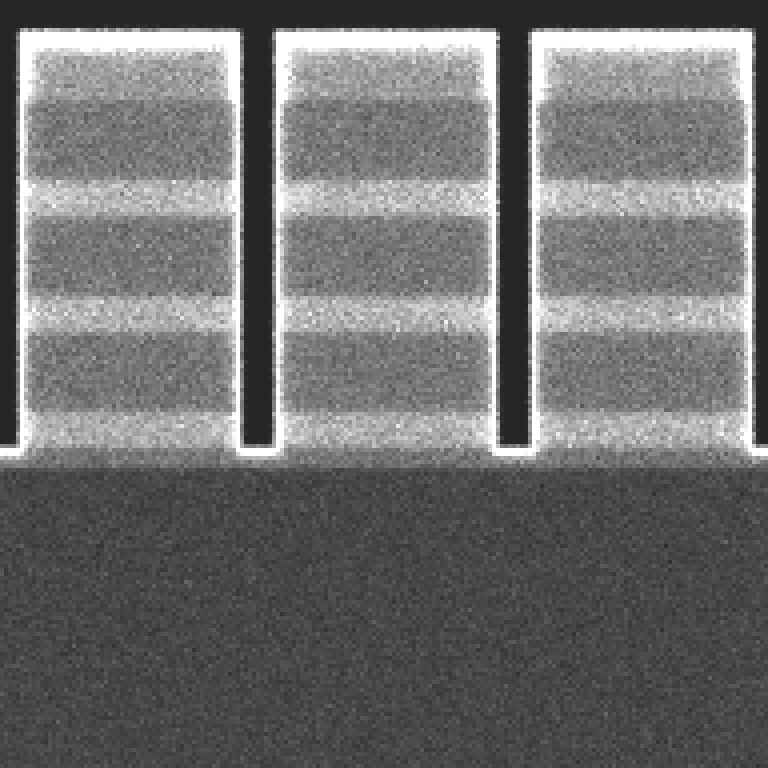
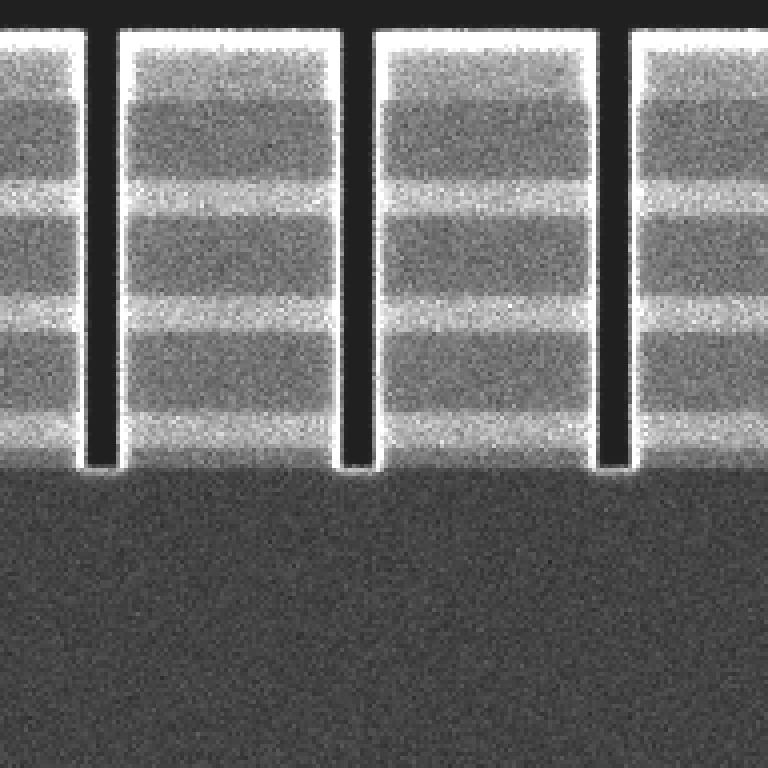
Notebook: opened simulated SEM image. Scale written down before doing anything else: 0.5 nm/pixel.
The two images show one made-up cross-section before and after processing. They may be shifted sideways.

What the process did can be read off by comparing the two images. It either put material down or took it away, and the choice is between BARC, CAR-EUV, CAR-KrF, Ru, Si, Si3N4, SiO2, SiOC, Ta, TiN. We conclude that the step removed Si3N4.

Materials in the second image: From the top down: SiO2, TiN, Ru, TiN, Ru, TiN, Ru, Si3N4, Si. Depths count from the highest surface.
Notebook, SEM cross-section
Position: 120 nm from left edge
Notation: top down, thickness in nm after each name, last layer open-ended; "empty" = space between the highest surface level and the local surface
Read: SiO2 34, TiN 40, Ru 18, TiN 40, Ru 18, TiN 40, Ru 18, Si3N4 10, Si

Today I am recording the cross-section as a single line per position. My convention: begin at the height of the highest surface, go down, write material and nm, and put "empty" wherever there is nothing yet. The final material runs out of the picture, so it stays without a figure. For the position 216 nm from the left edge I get SiO2 34, TiN 40, Ru 18, TiN 40, Ru 18, TiN 40, Ru 18, Si3N4 10, Si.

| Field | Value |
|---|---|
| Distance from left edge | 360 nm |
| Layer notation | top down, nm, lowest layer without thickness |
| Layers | SiO2 34, TiN 40, Ru 18, TiN 40, Ru 18, TiN 40, Ru 18, Si3N4 10, Si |